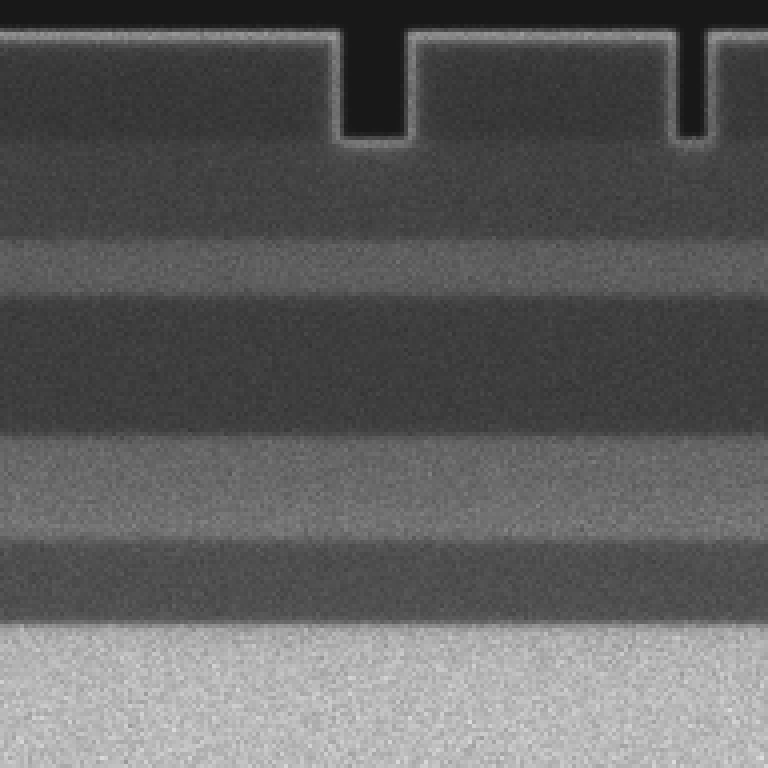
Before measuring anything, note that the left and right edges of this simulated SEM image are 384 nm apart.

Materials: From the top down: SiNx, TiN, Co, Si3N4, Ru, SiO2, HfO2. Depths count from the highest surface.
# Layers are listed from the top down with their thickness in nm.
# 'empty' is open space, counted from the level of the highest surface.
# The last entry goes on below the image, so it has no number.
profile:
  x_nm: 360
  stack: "SiNx 54, TiN 50, Co 28, Si3N4 70, Ru 52, SiO2 42, HfO2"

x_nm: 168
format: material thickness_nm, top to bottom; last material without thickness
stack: SiNx 54, TiN 50, Co 28, Si3N4 70, Ru 52, SiO2 42, HfO2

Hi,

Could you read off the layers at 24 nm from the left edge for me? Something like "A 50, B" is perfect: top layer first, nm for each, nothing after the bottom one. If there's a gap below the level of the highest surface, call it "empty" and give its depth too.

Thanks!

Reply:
SiNx 54, TiN 50, Co 28, Si3N4 70, Ru 52, SiO2 42, HfO2